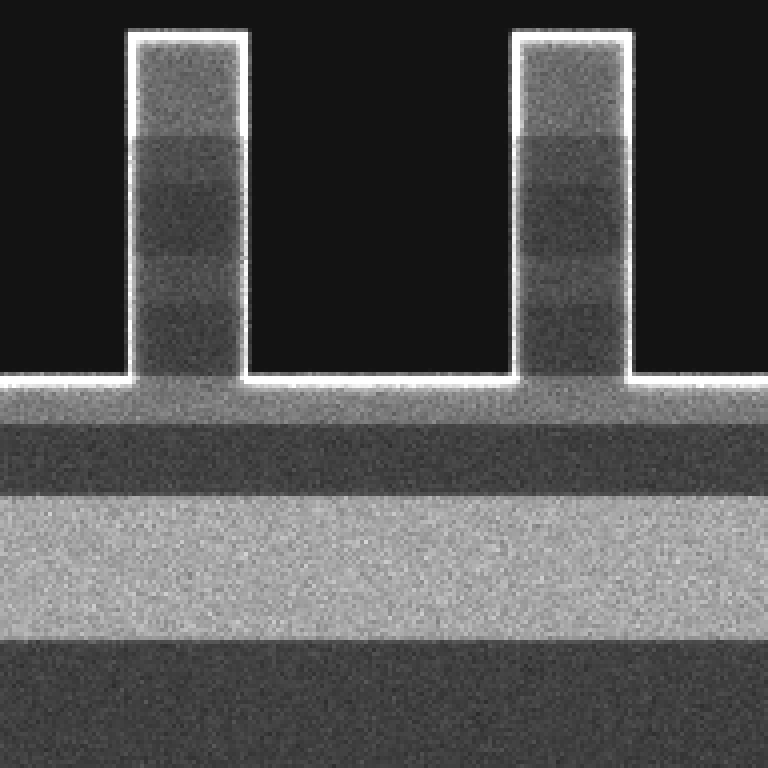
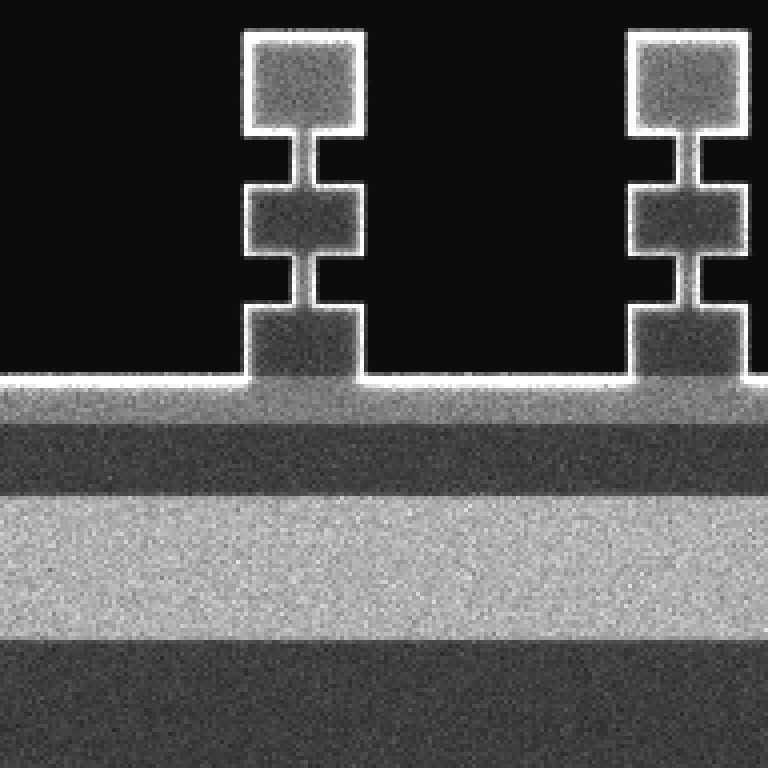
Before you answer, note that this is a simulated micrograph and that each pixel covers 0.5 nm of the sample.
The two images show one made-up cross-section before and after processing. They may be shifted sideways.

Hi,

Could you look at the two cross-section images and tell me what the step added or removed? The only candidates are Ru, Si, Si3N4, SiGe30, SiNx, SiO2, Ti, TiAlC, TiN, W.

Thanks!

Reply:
removed SiGe30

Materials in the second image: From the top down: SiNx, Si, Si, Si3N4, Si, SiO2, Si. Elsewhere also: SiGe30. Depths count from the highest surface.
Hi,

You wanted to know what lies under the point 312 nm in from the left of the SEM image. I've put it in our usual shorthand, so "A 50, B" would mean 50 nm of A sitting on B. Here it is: empty 172, Si3N4 24, Si 36, SiO2 72, Si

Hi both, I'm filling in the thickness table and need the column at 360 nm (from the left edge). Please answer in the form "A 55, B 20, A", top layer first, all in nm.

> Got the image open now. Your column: SiNx 52, empty 24, Si 36, empty 24, Si 36, Si3N4 24, Si 36, SiO2 72, Si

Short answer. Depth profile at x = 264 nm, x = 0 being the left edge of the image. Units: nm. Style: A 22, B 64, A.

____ empty 172, Si3N4 24, Si 36, SiO2 72, Si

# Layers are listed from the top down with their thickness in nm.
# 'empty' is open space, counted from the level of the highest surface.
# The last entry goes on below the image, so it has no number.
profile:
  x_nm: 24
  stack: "empty 172, Si3N4 24, Si 36, SiO2 72, Si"